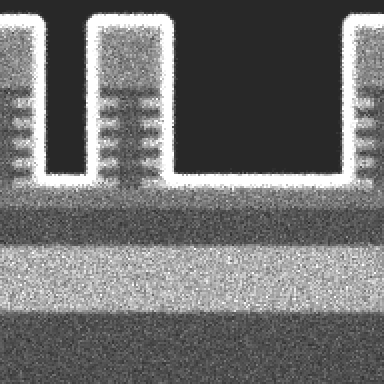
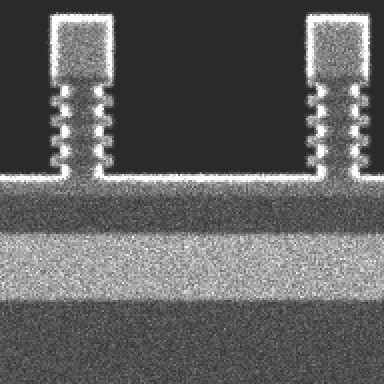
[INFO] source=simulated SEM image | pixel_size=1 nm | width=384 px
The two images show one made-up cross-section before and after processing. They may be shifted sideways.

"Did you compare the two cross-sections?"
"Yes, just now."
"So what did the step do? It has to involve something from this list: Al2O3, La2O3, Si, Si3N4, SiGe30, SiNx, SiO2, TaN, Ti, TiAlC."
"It removed Al2O3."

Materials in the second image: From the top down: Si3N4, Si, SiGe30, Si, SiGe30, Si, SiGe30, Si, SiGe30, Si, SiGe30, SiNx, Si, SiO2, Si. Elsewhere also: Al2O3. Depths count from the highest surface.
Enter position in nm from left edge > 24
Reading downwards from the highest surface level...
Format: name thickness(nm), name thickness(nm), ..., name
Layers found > empty 160, SiNx 20, Si 38, SiO2 66, Si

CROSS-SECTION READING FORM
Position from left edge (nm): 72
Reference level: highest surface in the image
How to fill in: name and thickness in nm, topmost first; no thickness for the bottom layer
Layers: Si3N4 60, Si 10, SiGe30 10, Si 10, SiGe30 10, Si 10, SiGe30 10, Si 10, SiGe30 10, Si 10, SiGe30 10, SiNx 20, Si 38, SiO2 66, Si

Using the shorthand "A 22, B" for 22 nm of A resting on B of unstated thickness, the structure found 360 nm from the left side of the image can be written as Si3N4 60, Si 10, empty 10, Si 10, empty 10, Si 10, empty 10, Si 10, empty 10, Si 10, empty 10, SiNx 20, Si 38, SiO2 66, Si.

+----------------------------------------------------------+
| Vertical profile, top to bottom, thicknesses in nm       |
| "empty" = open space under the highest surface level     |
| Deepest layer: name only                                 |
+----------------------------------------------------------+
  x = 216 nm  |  empty 160, SiNx 20, Si 38, SiO2 66, Si